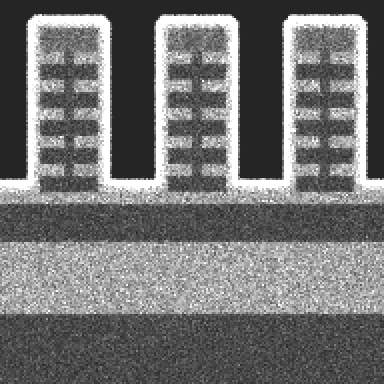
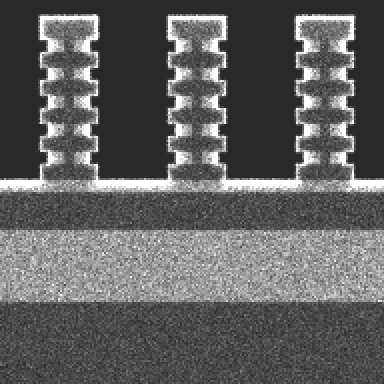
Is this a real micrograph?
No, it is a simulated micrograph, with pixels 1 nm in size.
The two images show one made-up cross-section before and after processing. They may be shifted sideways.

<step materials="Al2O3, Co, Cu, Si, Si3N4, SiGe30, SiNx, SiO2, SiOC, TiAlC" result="removed Al2O3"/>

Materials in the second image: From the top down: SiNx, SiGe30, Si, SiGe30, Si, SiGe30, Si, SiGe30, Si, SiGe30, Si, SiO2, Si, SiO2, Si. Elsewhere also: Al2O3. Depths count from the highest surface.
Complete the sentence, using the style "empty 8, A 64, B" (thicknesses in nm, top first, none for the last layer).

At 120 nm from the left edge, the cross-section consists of empty 164, SiO2 12, Si 38, SiO2 72, Si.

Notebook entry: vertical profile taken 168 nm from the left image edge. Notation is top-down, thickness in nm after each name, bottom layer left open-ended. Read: SiNx 24, empty 12, Si 16, empty 12, Si 16, empty 12, Si 16, empty 12, Si 16, empty 12, Si 16, SiO2 12, Si 38, SiO2 72, Si